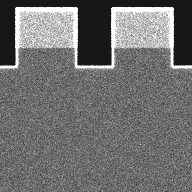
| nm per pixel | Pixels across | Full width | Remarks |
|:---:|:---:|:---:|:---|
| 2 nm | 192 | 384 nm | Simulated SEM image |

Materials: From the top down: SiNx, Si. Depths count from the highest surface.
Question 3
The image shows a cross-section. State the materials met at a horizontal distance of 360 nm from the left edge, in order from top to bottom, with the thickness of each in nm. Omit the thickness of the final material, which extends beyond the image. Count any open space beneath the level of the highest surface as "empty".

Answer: empty 116, Si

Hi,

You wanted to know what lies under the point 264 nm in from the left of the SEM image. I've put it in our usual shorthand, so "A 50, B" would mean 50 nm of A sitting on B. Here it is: SiNx 80, Si